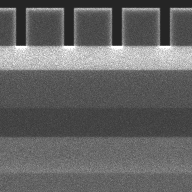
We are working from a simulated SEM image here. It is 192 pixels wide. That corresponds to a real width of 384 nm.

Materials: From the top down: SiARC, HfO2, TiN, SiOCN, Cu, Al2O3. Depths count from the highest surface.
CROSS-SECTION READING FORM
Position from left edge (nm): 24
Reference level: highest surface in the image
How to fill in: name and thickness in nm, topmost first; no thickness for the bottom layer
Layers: SiARC 76, HfO2 48, TiN 76, SiOCN 58, Cu 72, Al2O3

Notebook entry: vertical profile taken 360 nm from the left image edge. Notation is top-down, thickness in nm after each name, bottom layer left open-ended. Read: SiARC 76, HfO2 48, TiN 76, SiOCN 58, Cu 72, Al2O3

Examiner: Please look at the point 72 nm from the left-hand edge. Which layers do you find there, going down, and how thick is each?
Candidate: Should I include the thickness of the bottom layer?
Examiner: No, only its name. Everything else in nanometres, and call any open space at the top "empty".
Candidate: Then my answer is SiARC 76, HfO2 48, TiN 76, SiOCN 58, Cu 72, Al2O3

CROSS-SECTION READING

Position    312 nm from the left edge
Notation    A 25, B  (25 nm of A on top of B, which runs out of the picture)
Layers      SiARC 76, HfO2 48, TiN 76, SiOCN 58, Cu 72, Al2O3